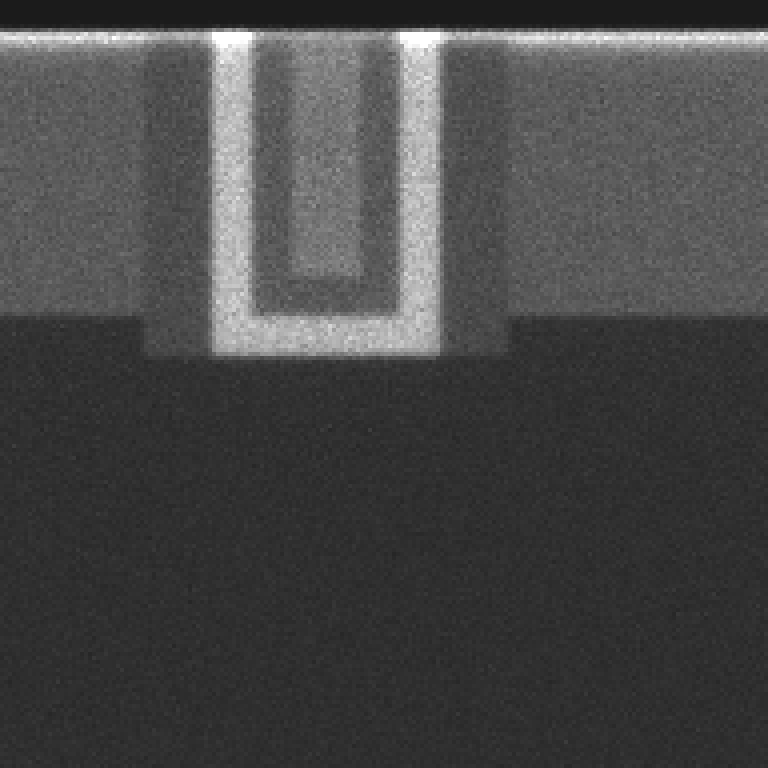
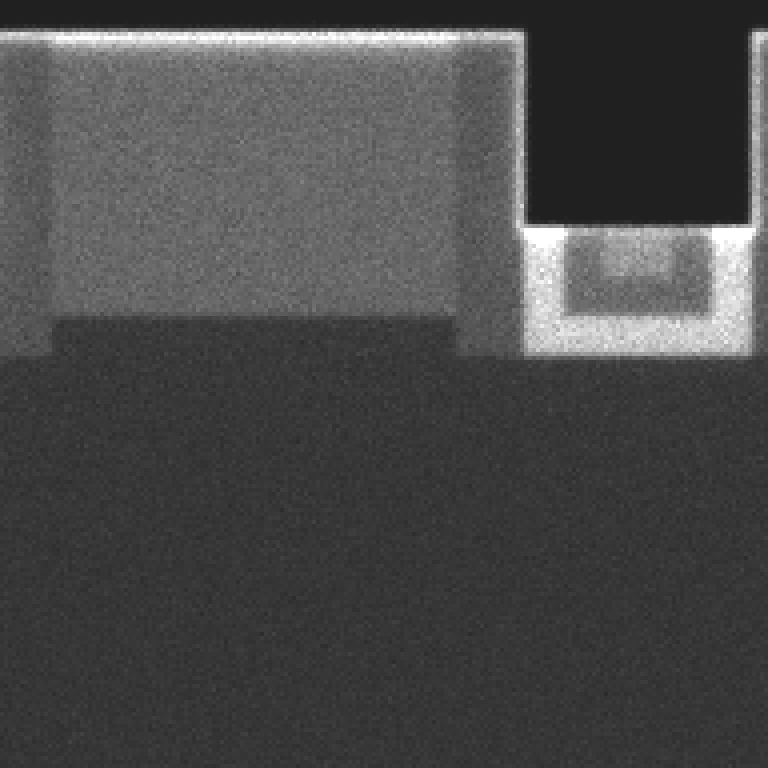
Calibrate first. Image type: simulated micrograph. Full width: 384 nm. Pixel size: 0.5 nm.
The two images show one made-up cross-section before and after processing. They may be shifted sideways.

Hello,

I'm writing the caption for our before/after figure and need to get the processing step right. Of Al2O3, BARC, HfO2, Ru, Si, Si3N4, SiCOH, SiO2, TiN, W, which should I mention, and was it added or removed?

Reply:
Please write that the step removed HfO2 and Ru and TiN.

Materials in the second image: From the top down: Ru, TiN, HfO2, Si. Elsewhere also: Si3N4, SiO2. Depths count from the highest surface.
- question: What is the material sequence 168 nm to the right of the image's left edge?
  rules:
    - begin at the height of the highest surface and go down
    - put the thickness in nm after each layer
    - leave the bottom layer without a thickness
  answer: SiO2 142, Si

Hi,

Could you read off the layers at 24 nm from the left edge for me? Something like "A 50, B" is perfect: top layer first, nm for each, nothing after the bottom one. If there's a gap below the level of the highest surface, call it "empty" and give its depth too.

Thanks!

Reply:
Si3N4 162, Si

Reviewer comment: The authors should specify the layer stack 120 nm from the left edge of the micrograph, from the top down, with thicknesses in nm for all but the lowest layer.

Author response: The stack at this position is SiO2 142, Si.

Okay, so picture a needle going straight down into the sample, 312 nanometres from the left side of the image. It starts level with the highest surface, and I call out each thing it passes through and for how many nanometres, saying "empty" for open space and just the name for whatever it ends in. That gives empty 98, Ru 24, TiN 20, HfO2 20, Si